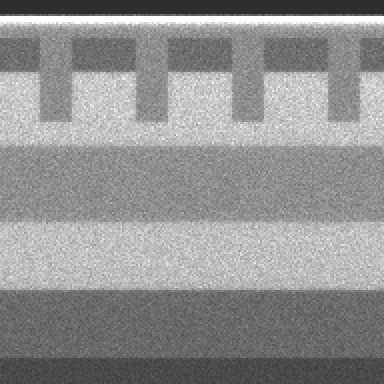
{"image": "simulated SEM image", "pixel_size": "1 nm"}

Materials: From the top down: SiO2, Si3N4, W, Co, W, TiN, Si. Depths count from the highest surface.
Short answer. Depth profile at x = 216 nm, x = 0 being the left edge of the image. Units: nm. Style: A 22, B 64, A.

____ SiO2 22, Si3N4 34, W 74, Co 76, W 68, TiN 68, Si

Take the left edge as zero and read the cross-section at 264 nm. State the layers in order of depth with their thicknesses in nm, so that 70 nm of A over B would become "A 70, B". SiO2 22, Si3N4 34, W 74, Co 76, W 68, TiN 68, Si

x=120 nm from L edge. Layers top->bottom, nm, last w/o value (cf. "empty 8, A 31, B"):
SiO2 22, Si3N4 34, W 74, Co 76, W 68, TiN 68, Si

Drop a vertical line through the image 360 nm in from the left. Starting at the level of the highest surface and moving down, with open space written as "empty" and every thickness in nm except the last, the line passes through SiO2 22, Si3N4 34, W 74, Co 76, W 68, TiN 68, Si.